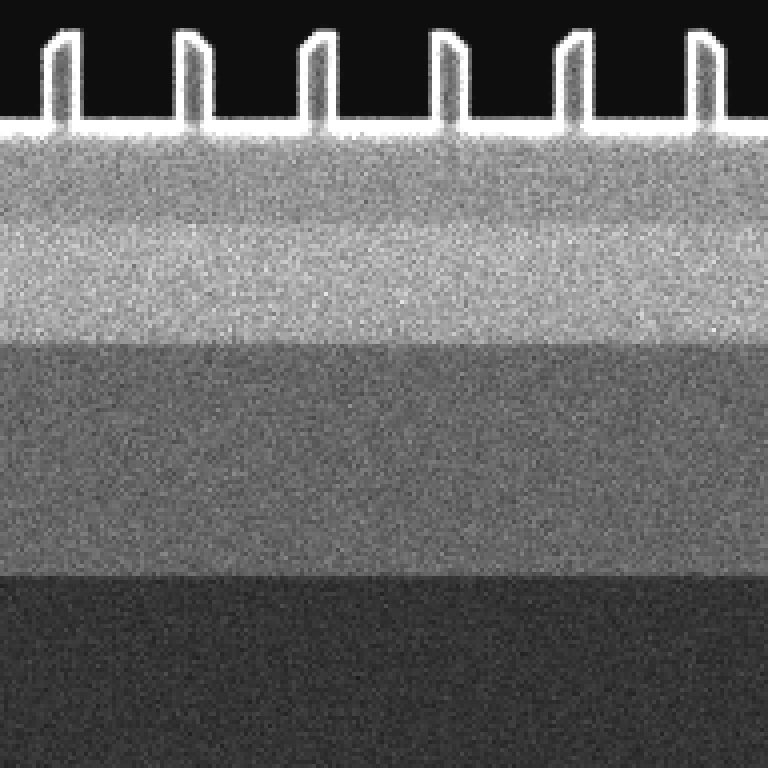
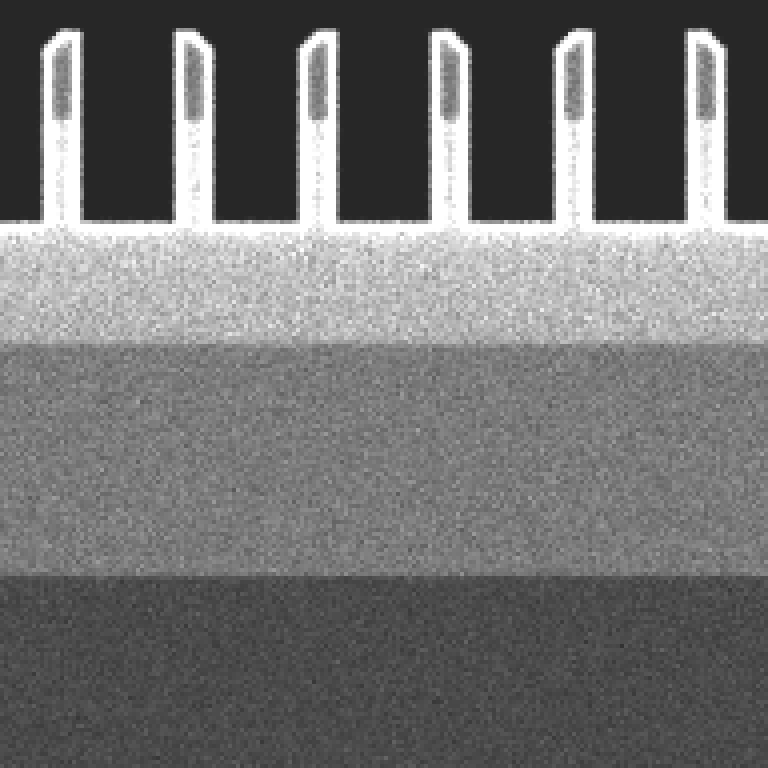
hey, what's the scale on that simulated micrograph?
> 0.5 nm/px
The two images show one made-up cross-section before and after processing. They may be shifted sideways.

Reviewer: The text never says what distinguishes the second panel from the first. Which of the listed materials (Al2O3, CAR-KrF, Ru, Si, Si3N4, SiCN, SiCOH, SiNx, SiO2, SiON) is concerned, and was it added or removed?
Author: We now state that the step removed SiO2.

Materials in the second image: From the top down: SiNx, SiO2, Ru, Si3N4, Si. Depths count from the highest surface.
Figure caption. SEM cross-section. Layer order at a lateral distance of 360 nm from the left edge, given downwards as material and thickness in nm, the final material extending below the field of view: empty 8, SiNx 36, SiO2 52, Ru 60, Si3N4 116, Si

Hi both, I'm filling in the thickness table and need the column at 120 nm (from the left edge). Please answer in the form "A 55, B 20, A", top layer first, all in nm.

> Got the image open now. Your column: empty 96, Ru 60, Si3N4 116, Si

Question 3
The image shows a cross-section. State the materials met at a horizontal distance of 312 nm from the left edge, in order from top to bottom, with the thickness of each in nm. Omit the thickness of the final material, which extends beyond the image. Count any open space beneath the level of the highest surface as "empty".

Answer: empty 96, Ru 60, Si3N4 116, Si